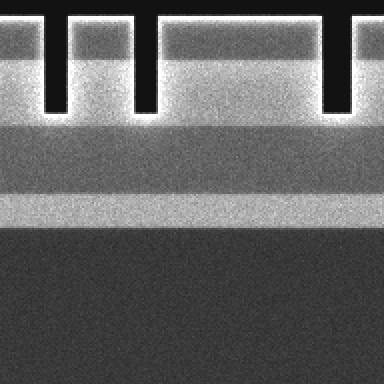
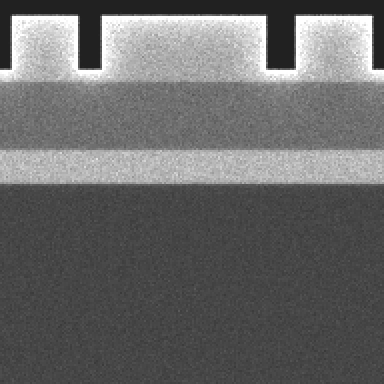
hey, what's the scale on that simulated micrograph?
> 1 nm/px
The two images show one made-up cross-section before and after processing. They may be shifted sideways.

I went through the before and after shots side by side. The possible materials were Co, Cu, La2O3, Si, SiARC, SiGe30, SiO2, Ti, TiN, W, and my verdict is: removed, SiARC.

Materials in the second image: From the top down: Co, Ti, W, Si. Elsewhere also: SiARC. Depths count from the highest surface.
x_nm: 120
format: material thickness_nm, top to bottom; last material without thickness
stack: Co 66, Ti 68, W 34, Si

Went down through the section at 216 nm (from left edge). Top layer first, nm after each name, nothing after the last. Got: Co 66, Ti 68, W 34, Si